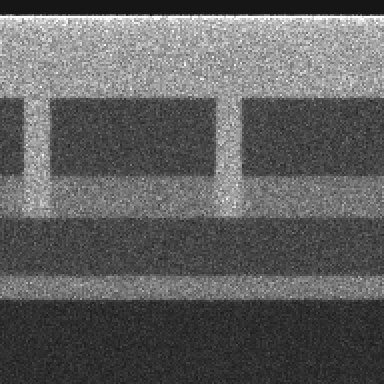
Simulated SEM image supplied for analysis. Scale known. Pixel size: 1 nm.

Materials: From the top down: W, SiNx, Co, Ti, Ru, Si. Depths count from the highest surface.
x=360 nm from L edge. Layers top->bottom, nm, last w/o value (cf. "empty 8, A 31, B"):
W 82, SiNx 78, Co 42, Ti 58, Ru 24, Si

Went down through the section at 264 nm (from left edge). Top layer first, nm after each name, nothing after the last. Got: W 82, SiNx 78, Co 42, Ti 58, Ru 24, Si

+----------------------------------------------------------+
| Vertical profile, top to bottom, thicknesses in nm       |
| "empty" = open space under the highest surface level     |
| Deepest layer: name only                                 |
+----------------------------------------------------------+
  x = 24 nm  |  W 202, Ti 58, Ru 24, Si